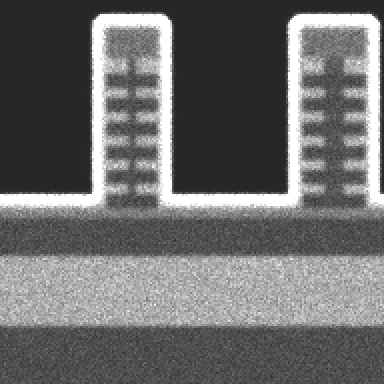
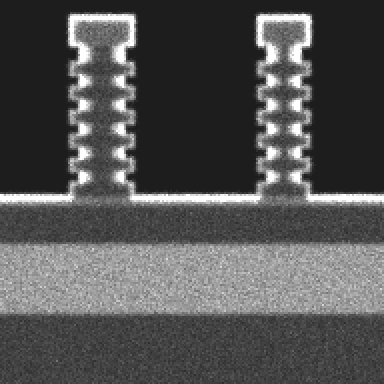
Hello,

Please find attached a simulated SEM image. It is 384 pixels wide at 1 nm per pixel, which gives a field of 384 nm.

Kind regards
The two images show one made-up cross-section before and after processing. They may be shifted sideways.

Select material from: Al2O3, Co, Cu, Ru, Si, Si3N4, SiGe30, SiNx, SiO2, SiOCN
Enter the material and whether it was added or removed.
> Al2O3 / removed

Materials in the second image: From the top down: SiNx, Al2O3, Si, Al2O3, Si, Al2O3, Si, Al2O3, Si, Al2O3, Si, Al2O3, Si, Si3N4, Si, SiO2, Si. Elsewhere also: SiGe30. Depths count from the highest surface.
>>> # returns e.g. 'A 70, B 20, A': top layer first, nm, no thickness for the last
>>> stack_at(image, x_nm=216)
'empty 180, Si3N4 10, Si 38, SiO2 70, Si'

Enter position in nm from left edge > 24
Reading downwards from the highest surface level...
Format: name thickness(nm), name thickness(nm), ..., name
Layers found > empty 180, Si3N4 10, Si 38, SiO2 70, Si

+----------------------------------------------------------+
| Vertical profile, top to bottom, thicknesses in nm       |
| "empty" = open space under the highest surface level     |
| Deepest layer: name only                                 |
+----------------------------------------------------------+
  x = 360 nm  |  empty 180, Si3N4 10, Si 38, SiO2 70, Si